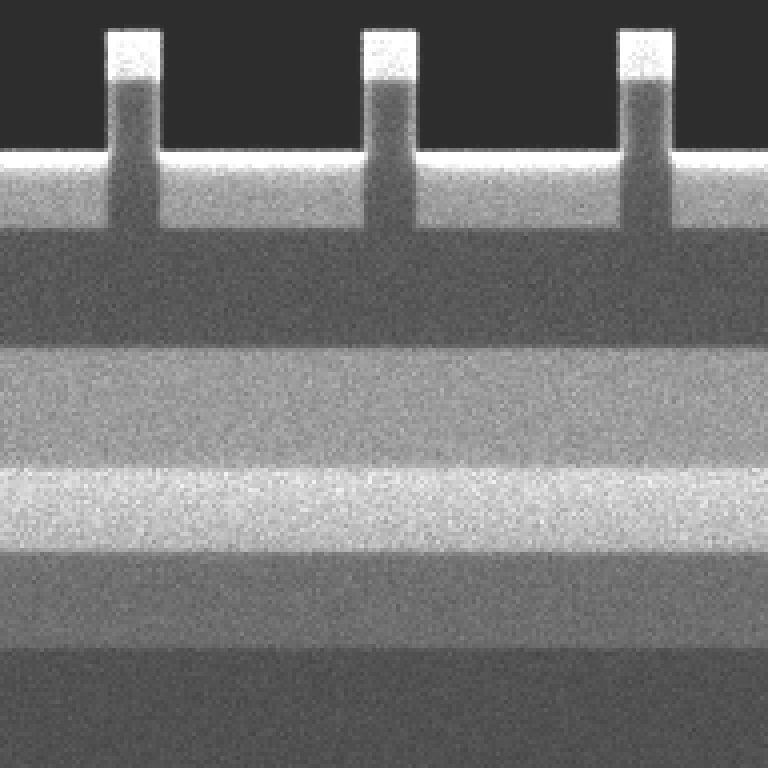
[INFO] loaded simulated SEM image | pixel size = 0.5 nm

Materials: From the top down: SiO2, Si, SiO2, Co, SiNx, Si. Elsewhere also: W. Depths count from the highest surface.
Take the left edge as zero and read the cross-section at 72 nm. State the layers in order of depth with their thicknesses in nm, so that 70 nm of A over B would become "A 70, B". W 24, Si 134, SiO2 60, Co 42, SiNx 48, Si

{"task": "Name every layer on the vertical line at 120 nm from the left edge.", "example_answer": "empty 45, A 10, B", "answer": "empty 60, SiO2 38, Si 60, SiO2 60, Co 42, SiNx 48, Si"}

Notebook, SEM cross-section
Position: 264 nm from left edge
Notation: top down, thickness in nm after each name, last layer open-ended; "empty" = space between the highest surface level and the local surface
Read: empty 60, SiO2 38, Si 60, SiO2 60, Co 42, SiNx 48, Si